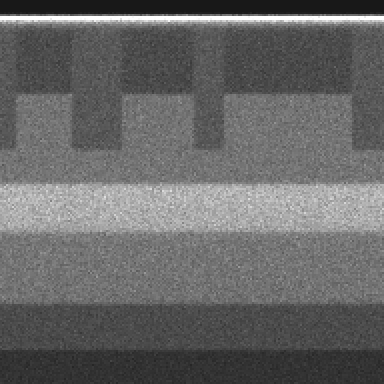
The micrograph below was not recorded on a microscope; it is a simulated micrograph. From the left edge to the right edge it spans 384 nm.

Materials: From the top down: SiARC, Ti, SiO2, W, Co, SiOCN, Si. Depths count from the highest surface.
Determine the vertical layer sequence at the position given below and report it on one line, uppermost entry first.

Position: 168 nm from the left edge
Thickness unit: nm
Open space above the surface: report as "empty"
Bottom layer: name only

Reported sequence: SiARC 10, Ti 68, SiO2 90, W 48, Co 72, SiOCN 46, Si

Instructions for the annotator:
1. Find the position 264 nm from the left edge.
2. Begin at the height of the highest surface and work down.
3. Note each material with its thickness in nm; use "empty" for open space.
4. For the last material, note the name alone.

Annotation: SiARC 10, Ti 68, SiO2 90, W 48, Co 72, SiOCN 46, Si